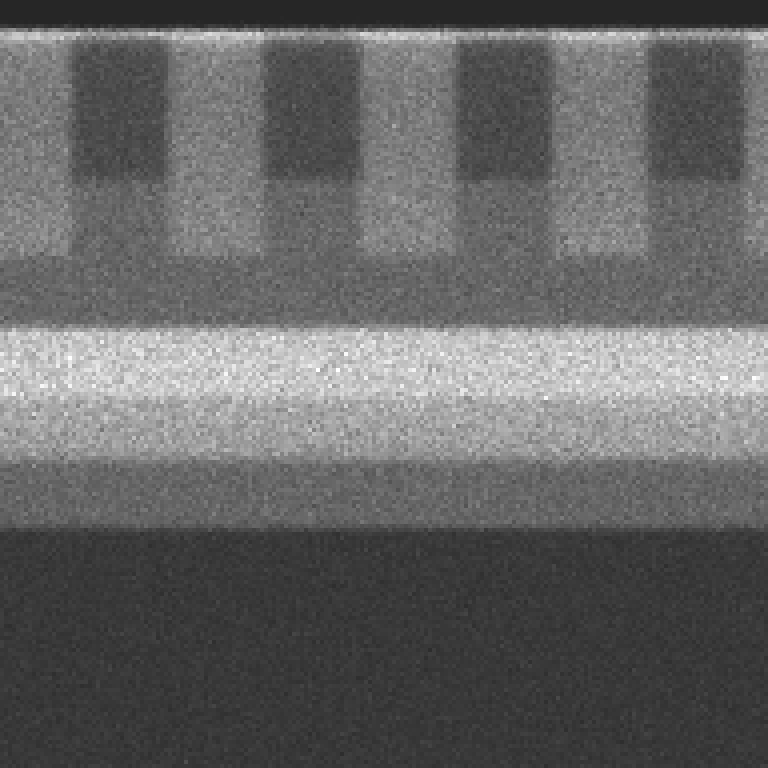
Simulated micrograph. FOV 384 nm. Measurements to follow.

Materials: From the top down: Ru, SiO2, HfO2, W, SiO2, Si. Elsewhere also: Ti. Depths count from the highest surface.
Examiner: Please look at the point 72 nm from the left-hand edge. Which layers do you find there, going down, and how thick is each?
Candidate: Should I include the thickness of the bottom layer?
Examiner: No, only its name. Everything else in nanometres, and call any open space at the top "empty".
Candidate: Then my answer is Ti 74, SiO2 74, HfO2 34, W 32, SiO2 34, Si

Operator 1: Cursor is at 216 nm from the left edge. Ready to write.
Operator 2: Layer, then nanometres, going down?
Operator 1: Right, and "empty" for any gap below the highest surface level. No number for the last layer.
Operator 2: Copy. Ru 112, SiO2 36, HfO2 34, W 32, SiO2 34, Si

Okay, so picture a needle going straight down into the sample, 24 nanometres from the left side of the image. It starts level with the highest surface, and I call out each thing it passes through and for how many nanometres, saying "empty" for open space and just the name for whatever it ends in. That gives Ru 112, SiO2 36, HfO2 34, W 32, SiO2 34, Si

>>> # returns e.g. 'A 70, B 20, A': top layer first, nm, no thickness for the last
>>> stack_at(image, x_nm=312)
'Ru 112, SiO2 36, HfO2 34, W 32, SiO2 34, Si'